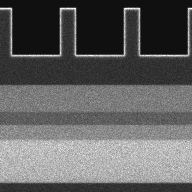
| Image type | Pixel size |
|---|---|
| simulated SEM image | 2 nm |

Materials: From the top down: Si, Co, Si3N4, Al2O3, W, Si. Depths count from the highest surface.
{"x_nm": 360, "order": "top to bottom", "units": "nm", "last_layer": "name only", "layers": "empty 94, Si 60, Co 54, Si3N4 26, Al2O3 30, W 86, Si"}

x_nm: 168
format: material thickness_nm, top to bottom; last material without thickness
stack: empty 94, Si 60, Co 54, Si3N4 26, Al2O3 30, W 86, Si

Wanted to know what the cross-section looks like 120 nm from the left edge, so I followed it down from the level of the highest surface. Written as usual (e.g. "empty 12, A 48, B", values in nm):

Si 154, Co 54, Si3N4 26, Al2O3 30, W 86, Si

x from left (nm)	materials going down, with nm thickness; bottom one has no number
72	empty 94, Si 60, Co 54, Si3N4 26, Al2O3 30, W 86, Si